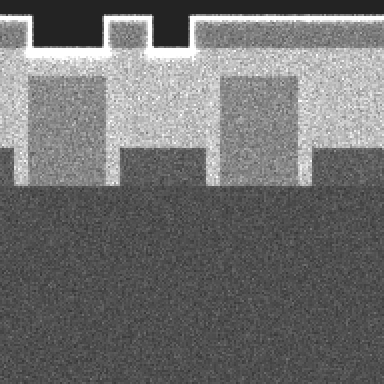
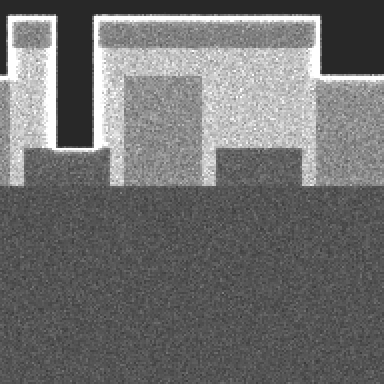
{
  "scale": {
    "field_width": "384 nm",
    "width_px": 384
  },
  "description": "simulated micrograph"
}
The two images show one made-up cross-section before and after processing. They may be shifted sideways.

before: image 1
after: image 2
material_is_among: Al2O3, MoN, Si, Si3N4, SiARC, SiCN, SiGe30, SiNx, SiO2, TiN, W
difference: SiO2, removed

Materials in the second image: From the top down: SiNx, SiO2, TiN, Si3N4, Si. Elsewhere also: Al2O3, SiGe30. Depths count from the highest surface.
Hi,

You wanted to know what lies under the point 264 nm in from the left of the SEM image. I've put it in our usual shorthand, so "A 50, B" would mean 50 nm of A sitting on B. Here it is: SiNx 32, SiO2 100, SiGe30 38, Si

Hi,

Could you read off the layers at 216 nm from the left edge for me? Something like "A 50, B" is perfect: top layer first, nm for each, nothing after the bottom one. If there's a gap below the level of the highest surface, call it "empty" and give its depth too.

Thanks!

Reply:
SiNx 32, SiO2 100, SiGe30 38, Si